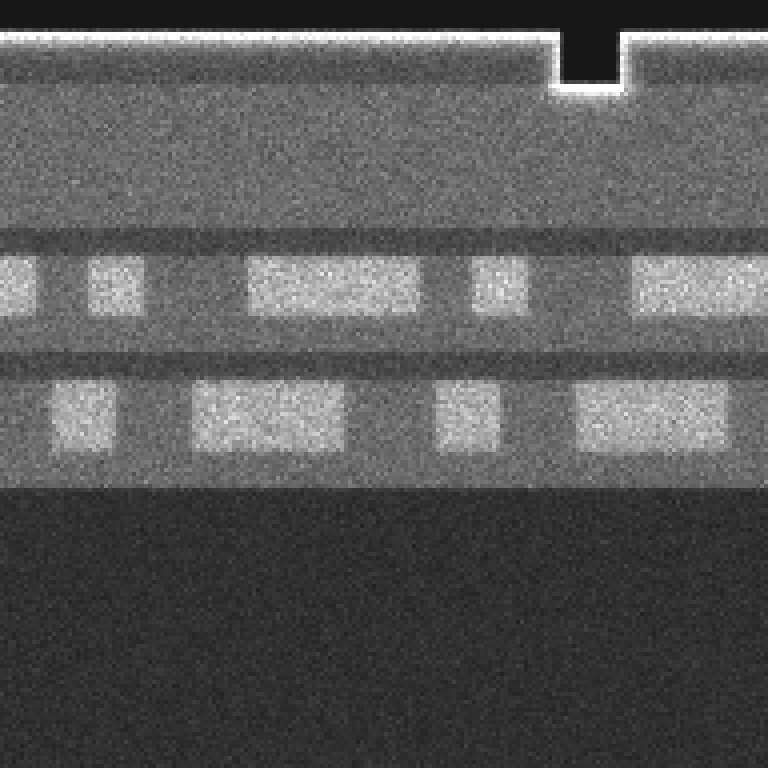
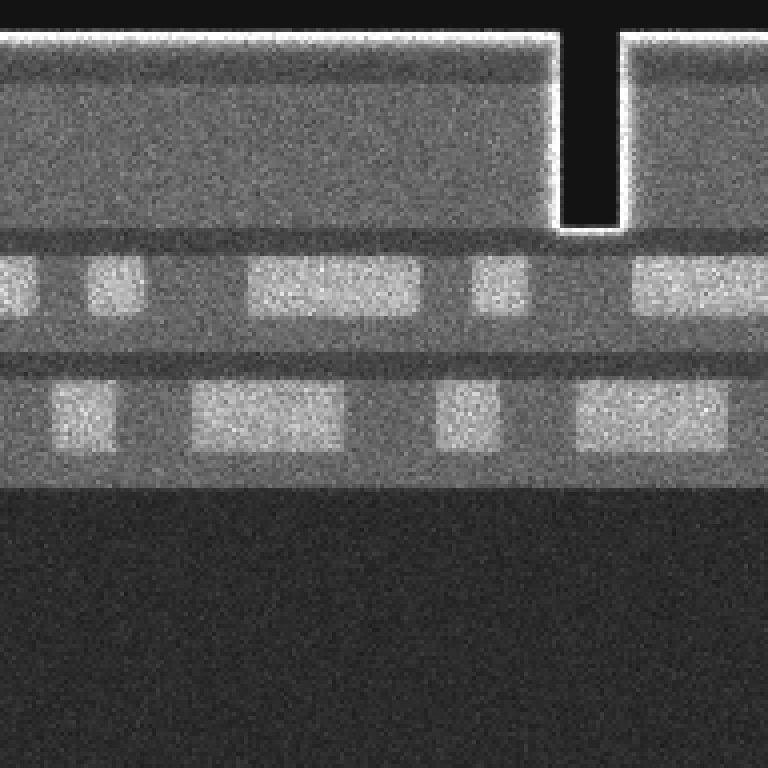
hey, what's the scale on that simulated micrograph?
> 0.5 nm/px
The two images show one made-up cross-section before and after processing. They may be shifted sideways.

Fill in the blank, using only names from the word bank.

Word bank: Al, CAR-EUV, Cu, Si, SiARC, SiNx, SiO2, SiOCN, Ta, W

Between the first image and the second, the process removed SiO2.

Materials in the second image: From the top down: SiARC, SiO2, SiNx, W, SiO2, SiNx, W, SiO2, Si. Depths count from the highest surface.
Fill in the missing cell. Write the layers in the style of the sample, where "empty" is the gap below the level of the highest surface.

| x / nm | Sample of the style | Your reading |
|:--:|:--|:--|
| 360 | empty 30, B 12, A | SiARC 26, SiO2 72, SiNx 14, W 30, SiO2 18, SiNx 14, W 36, SiO2 18, Si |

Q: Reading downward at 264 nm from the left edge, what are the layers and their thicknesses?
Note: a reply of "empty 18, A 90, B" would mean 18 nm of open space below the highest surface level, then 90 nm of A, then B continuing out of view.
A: SiARC 26, SiO2 72, SiNx 14, SiO2 48, SiNx 14, SiO2 54, Si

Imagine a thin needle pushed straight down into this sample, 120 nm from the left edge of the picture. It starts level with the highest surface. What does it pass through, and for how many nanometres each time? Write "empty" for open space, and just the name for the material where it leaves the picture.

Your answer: SiARC 26, SiO2 72, SiNx 14, SiO2 48, SiNx 14, W 36, SiO2 18, Si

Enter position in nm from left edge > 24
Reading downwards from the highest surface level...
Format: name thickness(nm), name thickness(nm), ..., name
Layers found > SiARC 26, SiO2 72, SiNx 14, SiO2 48, SiNx 14, SiO2 54, Si